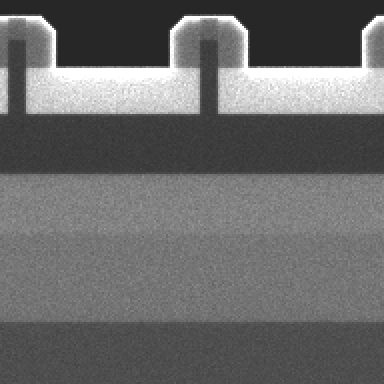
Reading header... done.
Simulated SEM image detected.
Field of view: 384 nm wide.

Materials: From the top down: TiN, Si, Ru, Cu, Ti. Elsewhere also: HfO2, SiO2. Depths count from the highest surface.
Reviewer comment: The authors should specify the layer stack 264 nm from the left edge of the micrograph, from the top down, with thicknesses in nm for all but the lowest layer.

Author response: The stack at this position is empty 52, HfO2 46, Si 60, Ru 60, Cu 88, Ti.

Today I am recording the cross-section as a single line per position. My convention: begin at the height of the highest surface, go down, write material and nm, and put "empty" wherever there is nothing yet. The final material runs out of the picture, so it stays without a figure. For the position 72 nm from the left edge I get empty 52, HfO2 46, Si 60, Ru 60, Cu 88, Ti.